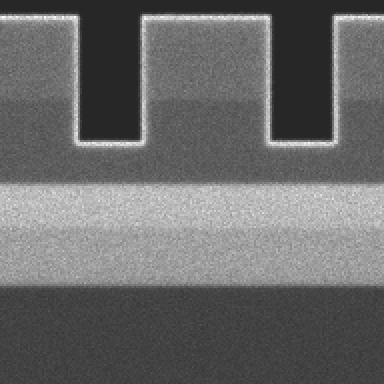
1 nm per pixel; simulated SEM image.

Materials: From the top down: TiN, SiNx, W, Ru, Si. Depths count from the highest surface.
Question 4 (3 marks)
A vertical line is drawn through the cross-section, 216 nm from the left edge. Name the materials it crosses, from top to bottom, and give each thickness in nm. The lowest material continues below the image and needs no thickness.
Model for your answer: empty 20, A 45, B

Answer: TiN 84, SiNx 84, W 44, Ru 58, Si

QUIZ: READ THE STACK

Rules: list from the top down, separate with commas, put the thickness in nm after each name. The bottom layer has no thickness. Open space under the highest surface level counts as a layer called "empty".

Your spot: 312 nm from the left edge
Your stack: empty 126, SiNx 42, W 44, Ru 58, Si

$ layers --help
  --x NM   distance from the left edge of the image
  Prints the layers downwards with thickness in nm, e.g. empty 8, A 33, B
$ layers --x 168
TiN 84, SiNx 84, W 44, Ru 58, Si